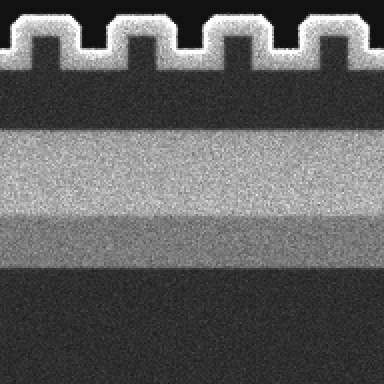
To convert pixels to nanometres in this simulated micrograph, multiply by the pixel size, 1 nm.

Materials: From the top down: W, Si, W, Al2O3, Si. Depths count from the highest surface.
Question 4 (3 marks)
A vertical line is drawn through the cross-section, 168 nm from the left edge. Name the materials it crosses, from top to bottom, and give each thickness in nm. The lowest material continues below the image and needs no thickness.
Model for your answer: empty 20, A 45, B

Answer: empty 4, W 50, Si 60, W 86, Al2O3 52, Si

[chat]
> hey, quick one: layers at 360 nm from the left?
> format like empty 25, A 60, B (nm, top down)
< empty 4, W 50, Si 60, W 86, Al2O3 52, Si